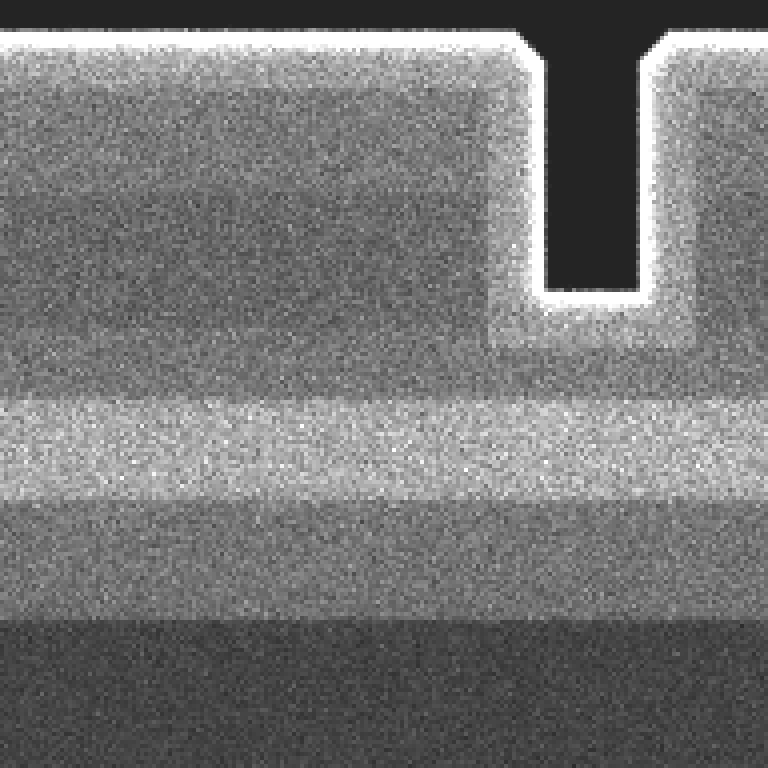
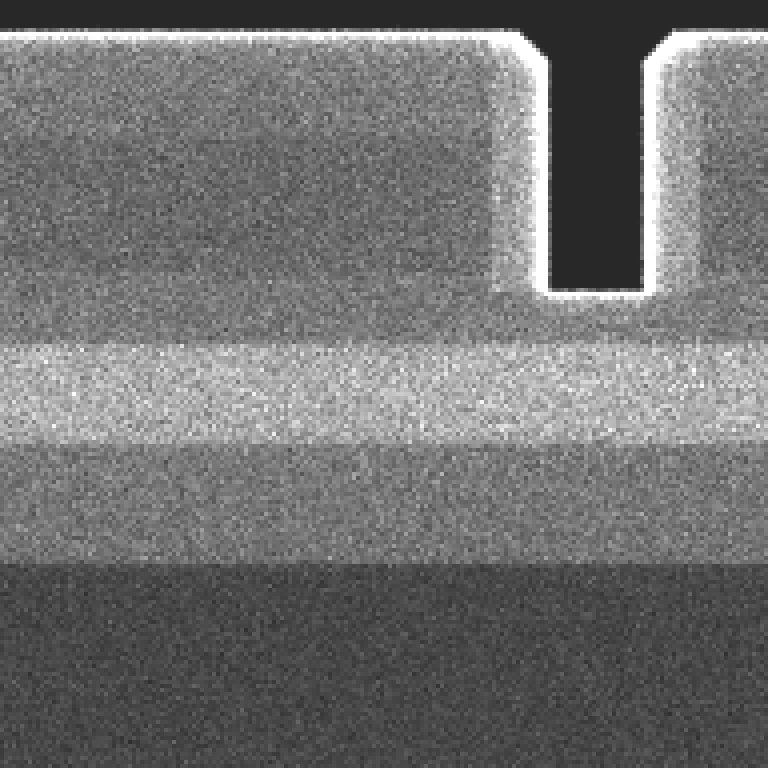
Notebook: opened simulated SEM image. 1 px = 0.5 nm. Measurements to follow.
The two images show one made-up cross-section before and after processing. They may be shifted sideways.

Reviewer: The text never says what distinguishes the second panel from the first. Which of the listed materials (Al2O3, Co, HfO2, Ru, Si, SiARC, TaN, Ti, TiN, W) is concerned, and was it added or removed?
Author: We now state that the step removed Al2O3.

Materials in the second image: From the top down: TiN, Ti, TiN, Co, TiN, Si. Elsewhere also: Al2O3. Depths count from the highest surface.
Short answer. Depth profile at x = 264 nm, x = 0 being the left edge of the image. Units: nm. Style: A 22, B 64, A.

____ empty 6, Al2O3 124, TiN 26, Co 50, TiN 60, Si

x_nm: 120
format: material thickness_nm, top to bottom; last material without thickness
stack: TiN 52, Ti 68, TiN 36, Co 50, TiN 60, Si